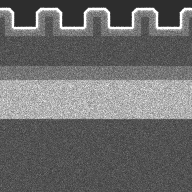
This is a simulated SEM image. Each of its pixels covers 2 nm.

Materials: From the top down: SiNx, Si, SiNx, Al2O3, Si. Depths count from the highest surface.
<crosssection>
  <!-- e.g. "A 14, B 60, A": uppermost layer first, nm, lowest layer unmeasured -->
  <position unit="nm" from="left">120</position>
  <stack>empty 6, SiNx 50, Si 60, SiNx 28, Al2O3 78, Si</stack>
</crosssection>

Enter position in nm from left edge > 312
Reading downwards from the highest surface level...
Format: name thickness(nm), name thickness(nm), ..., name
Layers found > empty 6, SiNx 50, Si 60, SiNx 28, Al2O3 78, Si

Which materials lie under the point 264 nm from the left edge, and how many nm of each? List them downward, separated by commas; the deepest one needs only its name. empty 8, SiNx 48, Si 60, SiNx 28, Al2O3 78, Si